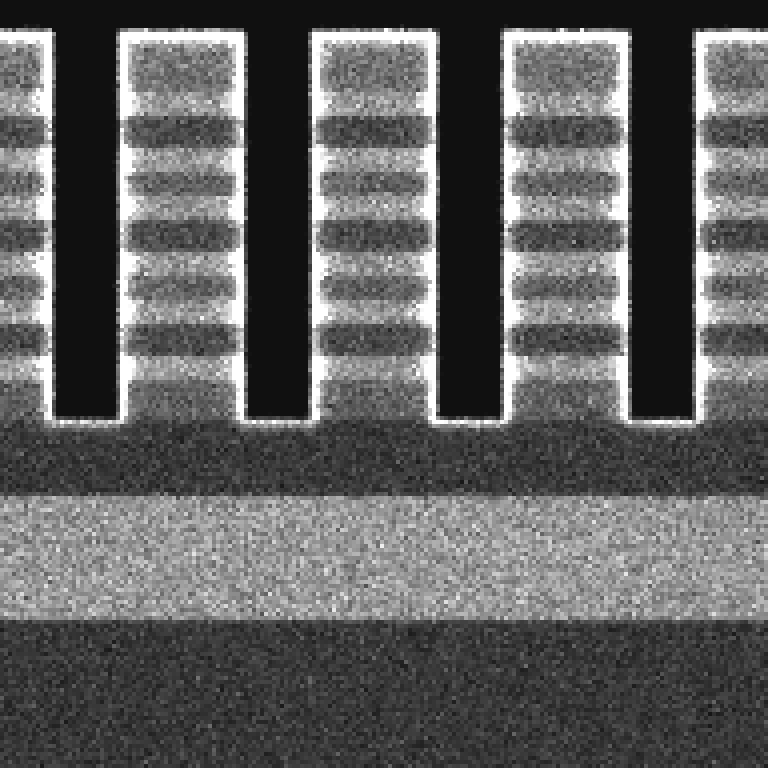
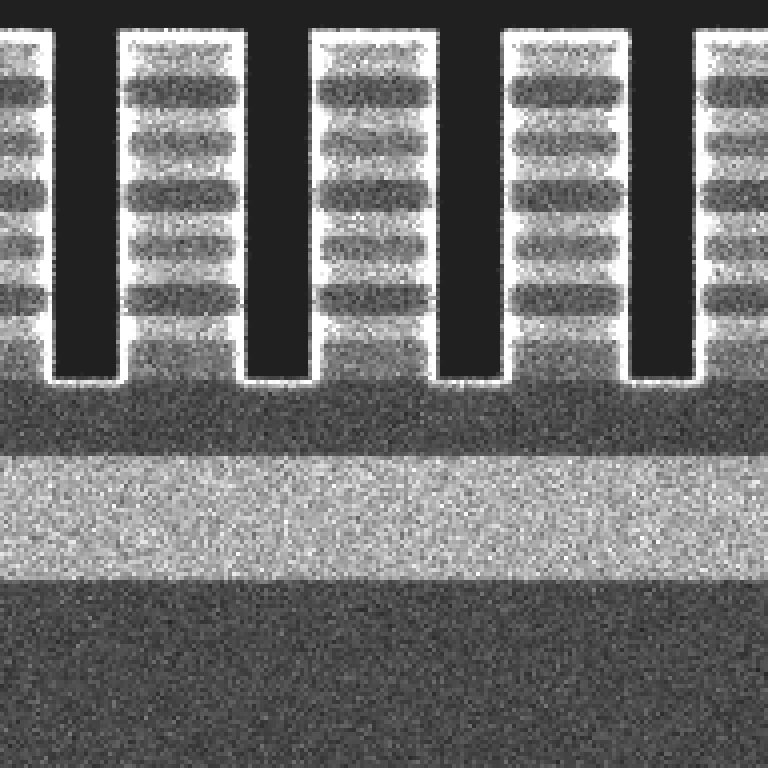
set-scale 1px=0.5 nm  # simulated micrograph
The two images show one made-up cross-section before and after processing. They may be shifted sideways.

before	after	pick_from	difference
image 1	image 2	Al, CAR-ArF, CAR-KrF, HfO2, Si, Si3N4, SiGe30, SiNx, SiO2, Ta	Si3N4 removed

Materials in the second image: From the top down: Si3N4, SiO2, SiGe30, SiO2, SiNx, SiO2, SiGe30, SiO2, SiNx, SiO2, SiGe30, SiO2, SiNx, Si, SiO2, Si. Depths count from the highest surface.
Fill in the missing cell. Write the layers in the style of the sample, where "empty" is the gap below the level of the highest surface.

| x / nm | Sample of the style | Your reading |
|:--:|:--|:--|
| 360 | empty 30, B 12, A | Si3N4 10, SiO2 12, SiGe30 16, SiO2 12, SiNx 12, SiO2 12, SiGe30 16, SiO2 12, SiNx 12, SiO2 12, SiGe30 16, SiO2 12, SiNx 20, Si 38, SiO2 62, Si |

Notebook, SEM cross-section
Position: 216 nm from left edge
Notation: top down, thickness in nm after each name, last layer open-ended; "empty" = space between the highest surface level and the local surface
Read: Si3N4 10, SiO2 12, SiGe30 16, SiO2 12, SiNx 12, SiO2 12, SiGe30 16, SiO2 12, SiNx 12, SiO2 12, SiGe30 16, SiO2 12, SiNx 20, Si 38, SiO2 62, Si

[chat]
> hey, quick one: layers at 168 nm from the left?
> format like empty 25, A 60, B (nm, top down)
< Si3N4 10, SiO2 12, SiGe30 16, SiO2 12, SiNx 12, SiO2 12, SiGe30 16, SiO2 12, SiNx 12, SiO2 12, SiGe30 16, SiO2 12, SiNx 20, Si 38, SiO2 62, Si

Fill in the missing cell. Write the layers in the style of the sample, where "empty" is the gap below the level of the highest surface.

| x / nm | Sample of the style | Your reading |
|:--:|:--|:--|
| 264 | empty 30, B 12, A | Si3N4 10, SiO2 12, SiGe30 16, SiO2 12, SiNx 12, SiO2 12, SiGe30 16, SiO2 12, SiNx 12, SiO2 12, SiGe30 16, SiO2 12, SiNx 20, Si 38, SiO2 62, Si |